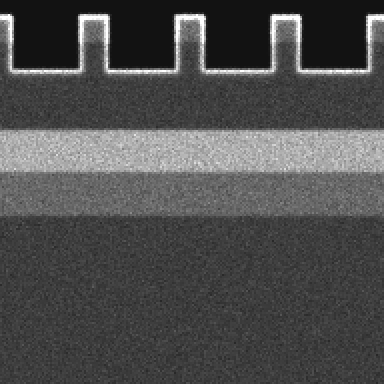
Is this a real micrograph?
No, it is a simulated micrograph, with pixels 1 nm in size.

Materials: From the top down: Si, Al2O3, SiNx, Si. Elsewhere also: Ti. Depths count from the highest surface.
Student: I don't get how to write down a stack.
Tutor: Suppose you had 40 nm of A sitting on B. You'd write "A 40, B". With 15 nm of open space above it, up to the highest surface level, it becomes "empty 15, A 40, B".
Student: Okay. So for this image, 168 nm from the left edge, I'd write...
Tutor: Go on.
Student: empty 54, Si 60, Al2O3 42, SiNx 44, Si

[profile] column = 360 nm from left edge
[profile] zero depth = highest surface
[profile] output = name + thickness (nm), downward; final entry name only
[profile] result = empty 54, Si 60, Al2O3 42, SiNx 44, Si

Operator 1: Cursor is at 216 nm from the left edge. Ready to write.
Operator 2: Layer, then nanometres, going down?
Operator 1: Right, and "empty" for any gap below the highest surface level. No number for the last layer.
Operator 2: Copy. empty 54, Si 60, Al2O3 42, SiNx 44, Si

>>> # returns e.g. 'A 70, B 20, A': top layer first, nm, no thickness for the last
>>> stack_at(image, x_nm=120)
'empty 54, Si 60, Al2O3 42, SiNx 44, Si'